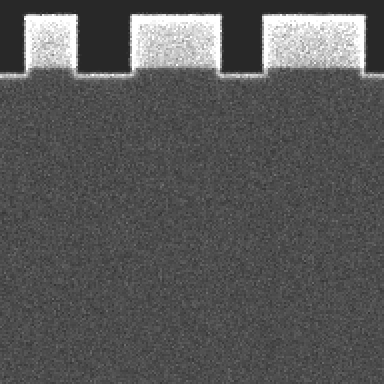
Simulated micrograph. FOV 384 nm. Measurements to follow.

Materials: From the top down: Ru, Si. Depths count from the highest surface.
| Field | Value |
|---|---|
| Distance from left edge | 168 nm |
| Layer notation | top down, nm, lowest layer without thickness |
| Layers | Ru 52, Si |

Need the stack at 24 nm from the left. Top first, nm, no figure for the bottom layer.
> empty 58, Si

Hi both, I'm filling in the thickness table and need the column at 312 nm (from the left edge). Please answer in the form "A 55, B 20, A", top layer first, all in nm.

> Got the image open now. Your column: Ru 52, Si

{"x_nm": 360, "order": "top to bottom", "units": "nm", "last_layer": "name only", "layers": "Ru 52, Si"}